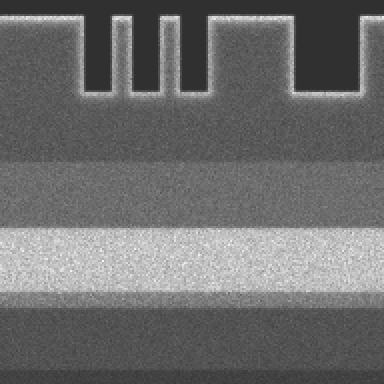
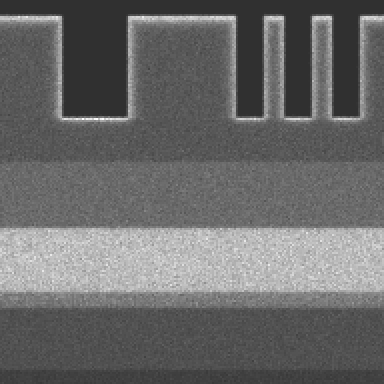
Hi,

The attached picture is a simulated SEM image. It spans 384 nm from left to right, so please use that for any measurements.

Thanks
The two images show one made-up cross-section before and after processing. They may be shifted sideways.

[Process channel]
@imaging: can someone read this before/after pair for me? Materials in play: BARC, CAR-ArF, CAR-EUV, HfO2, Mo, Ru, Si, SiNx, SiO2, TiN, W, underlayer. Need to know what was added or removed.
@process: underlayer removed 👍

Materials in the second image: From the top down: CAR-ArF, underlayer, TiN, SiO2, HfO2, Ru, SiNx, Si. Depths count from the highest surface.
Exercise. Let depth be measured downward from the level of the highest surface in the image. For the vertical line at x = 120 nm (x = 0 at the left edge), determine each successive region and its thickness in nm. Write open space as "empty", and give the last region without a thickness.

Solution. empty 102, TiN 44, SiO2 66, HfO2 64, Ru 16, SiNx 62, Si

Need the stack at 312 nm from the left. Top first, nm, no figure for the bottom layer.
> CAR-ArF 76, underlayer 26, TiN 44, SiO2 66, HfO2 64, Ru 16, SiNx 62, Si